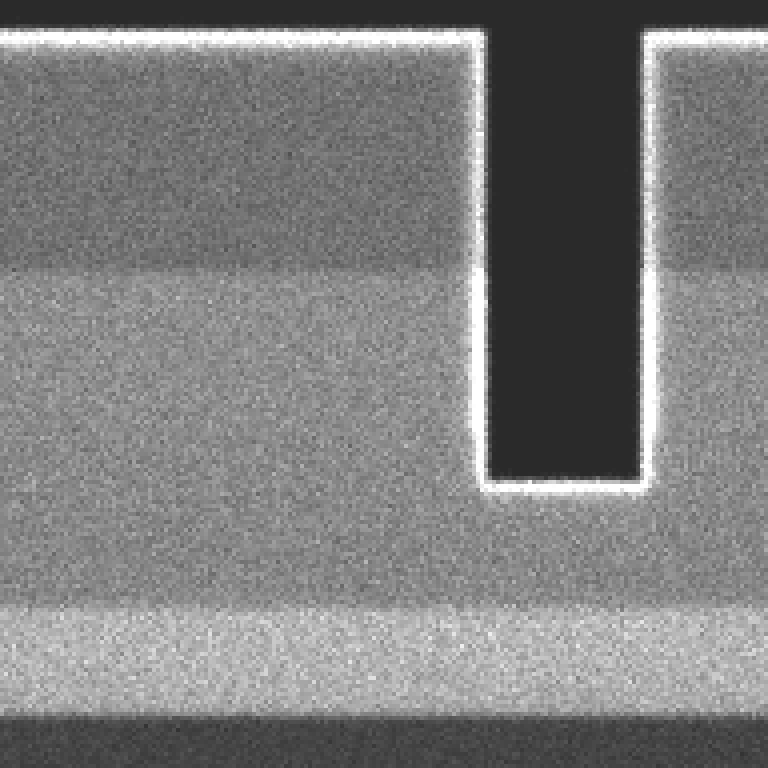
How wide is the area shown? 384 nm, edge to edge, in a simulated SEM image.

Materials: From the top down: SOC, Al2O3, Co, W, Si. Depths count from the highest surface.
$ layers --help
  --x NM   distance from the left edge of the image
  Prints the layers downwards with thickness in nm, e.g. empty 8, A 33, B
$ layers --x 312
empty 226, Co 62, W 54, Si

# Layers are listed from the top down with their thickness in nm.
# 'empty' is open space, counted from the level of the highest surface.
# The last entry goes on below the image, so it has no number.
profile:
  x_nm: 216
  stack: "SOC 120, Al2O3 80, Co 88, W 54, Si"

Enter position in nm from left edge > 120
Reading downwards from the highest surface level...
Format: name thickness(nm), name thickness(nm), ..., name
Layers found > SOC 120, Al2O3 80, Co 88, W 54, Si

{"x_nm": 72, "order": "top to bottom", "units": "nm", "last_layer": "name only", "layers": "SOC 120, Al2O3 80, Co 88, W 54, Si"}